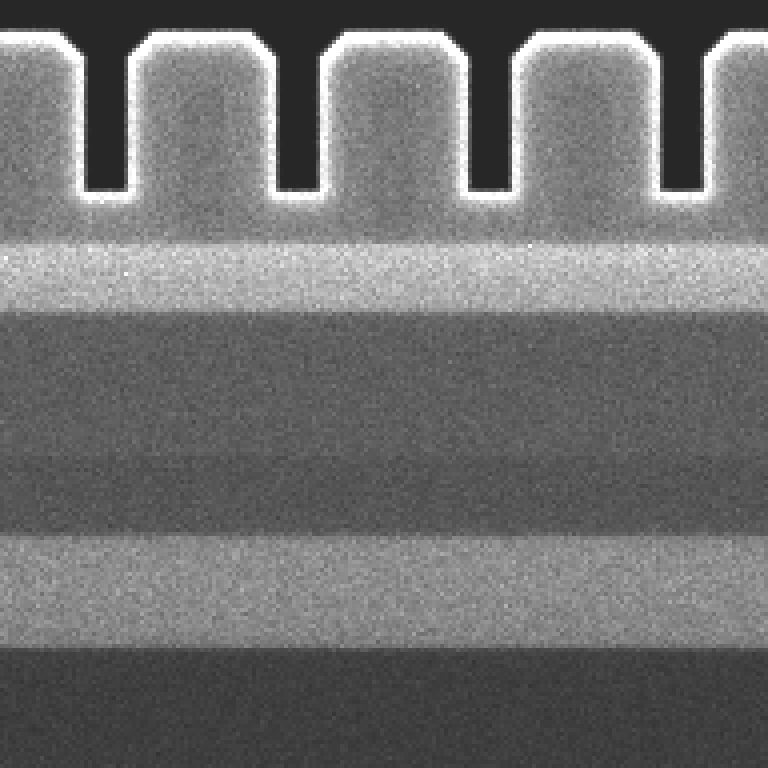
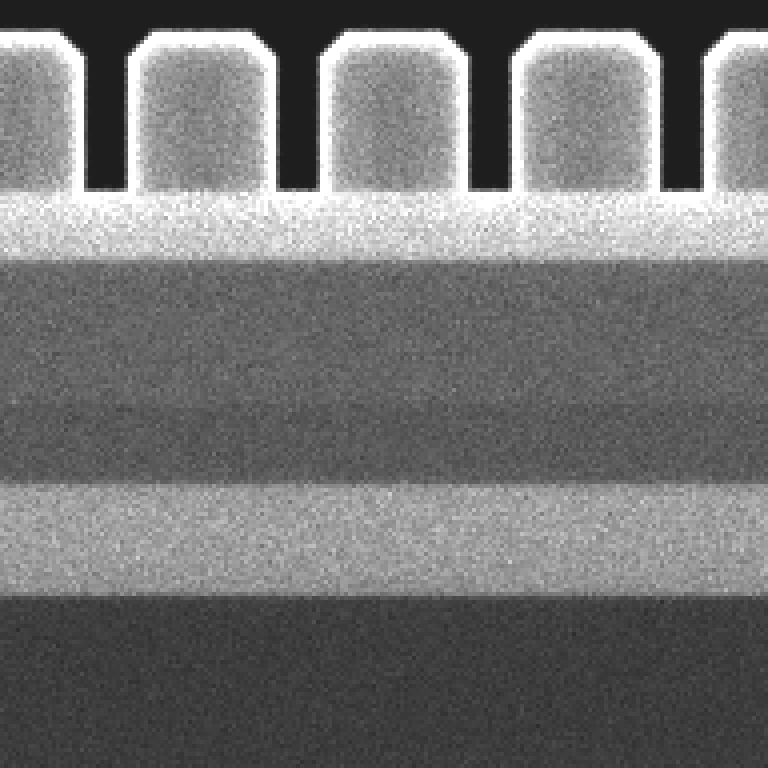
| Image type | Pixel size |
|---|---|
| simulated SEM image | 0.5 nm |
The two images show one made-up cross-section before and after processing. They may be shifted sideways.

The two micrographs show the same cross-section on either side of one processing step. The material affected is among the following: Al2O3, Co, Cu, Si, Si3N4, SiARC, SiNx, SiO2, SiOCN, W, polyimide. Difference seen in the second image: Al2O3 removed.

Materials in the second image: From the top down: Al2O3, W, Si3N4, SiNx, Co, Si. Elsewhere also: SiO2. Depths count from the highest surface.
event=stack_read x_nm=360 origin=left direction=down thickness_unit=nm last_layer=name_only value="empty 4, Al2O3 76, W 34, Si3N4 72, SiNx 40, Co 56, Si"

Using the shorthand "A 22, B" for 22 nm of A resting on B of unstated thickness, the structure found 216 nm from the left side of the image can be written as Al2O3 80, W 34, Si3N4 72, SiNx 40, Co 56, Si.